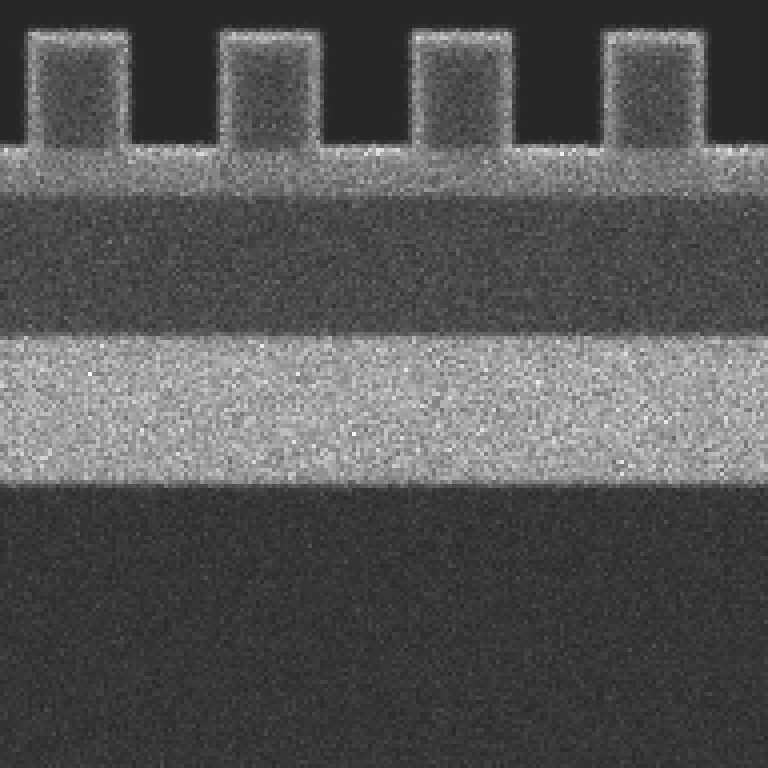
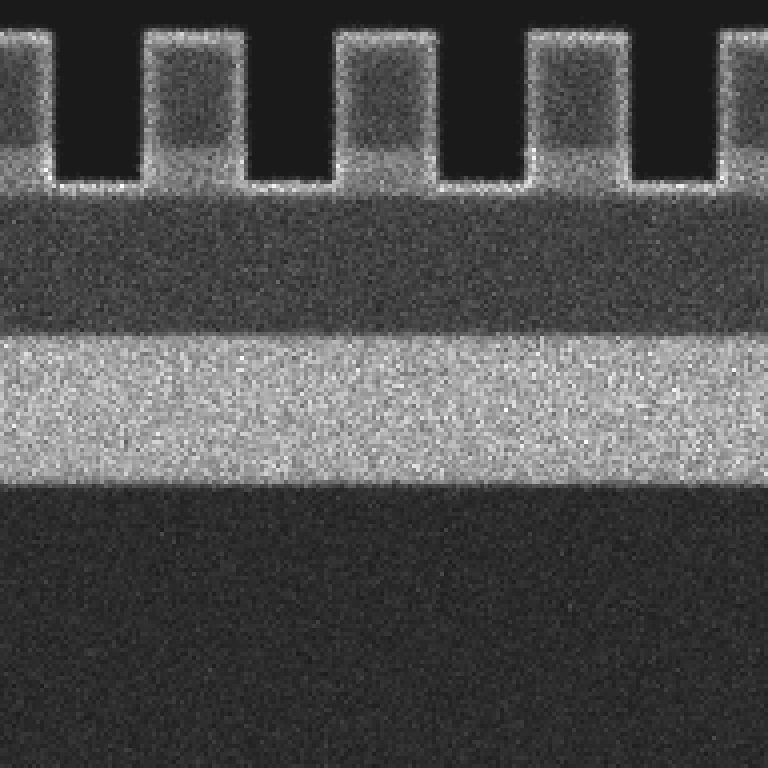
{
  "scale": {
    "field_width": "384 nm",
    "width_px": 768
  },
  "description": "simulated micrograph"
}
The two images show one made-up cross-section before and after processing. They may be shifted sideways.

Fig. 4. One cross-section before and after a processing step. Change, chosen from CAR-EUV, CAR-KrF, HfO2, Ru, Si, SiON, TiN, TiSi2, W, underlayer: W removed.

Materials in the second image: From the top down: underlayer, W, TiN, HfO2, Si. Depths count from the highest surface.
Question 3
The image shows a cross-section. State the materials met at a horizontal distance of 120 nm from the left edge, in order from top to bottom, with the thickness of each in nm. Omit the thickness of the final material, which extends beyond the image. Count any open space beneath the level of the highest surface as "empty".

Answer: underlayer 58, W 24, TiN 70, HfO2 74, Si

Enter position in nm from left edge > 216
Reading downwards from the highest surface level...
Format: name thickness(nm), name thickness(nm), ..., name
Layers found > underlayer 58, W 24, TiN 70, HfO2 74, Si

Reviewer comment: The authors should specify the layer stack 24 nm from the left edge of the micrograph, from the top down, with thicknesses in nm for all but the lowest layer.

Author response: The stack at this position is underlayer 58, W 24, TiN 70, HfO2 74, Si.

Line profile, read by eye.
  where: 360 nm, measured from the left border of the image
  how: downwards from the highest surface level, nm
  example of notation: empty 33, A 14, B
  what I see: underlayer 58, W 24, TiN 70, HfO2 74, Si